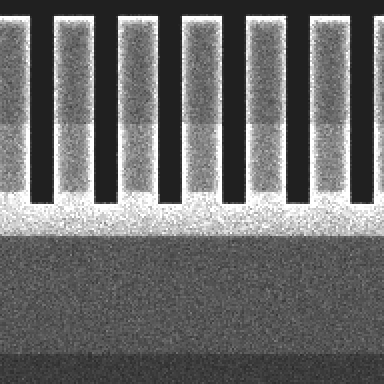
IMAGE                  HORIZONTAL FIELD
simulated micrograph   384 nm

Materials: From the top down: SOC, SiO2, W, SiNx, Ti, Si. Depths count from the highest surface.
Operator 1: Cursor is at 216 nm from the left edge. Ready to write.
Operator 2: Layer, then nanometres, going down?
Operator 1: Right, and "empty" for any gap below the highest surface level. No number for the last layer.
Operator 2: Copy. SOC 108, SiO2 68, W 44, SiNx 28, Ti 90, Si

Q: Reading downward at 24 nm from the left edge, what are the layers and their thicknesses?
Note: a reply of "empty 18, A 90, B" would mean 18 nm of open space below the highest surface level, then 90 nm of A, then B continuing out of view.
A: SOC 108, SiO2 68, W 44, SiNx 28, Ti 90, Si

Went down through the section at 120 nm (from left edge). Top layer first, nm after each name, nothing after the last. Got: SOC 108, SiO2 68, W 44, SiNx 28, Ti 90, Si